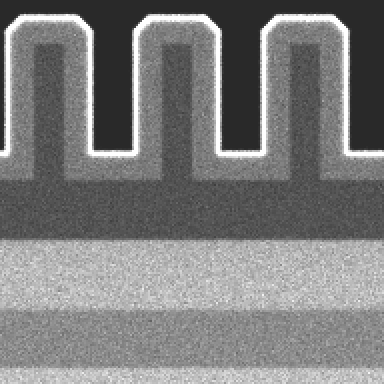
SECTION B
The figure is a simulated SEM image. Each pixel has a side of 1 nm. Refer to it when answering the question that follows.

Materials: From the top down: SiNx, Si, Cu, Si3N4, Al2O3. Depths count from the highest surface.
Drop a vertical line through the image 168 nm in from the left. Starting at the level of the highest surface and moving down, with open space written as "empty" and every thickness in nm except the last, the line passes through SiNx 28, Si 196, Cu 70, Si3N4 58, Al2O3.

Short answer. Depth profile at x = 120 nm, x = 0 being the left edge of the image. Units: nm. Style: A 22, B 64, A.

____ empty 136, SiNx 28, Si 60, Cu 70, Si3N4 58, Al2O3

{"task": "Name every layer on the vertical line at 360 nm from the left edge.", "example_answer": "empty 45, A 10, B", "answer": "empty 136, SiNx 28, Si 60, Cu 70, Si3N4 58, Al2O3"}